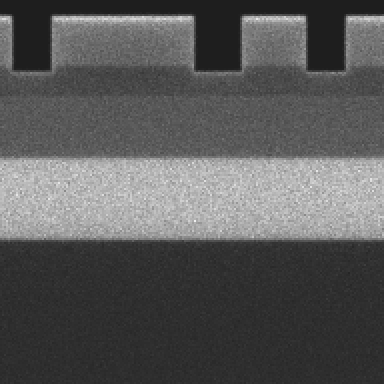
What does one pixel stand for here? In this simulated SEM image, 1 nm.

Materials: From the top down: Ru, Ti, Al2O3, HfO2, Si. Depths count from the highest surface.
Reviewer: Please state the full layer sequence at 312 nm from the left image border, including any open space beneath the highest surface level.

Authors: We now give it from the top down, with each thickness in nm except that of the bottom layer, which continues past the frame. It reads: empty 56, Ti 24, Al2O3 62, HfO2 82, Si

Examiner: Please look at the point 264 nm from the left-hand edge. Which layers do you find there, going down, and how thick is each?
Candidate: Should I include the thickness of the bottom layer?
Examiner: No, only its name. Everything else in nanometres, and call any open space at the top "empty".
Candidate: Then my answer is Ru 50, Ti 30, Al2O3 62, HfO2 82, Si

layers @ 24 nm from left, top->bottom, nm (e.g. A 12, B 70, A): empty 56, Ti 24, Al2O3 62, HfO2 82, Si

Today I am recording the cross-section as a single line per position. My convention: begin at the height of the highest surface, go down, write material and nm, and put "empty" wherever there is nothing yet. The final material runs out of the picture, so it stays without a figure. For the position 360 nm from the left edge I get Ru 50, Ti 30, Al2O3 62, HfO2 82, Si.